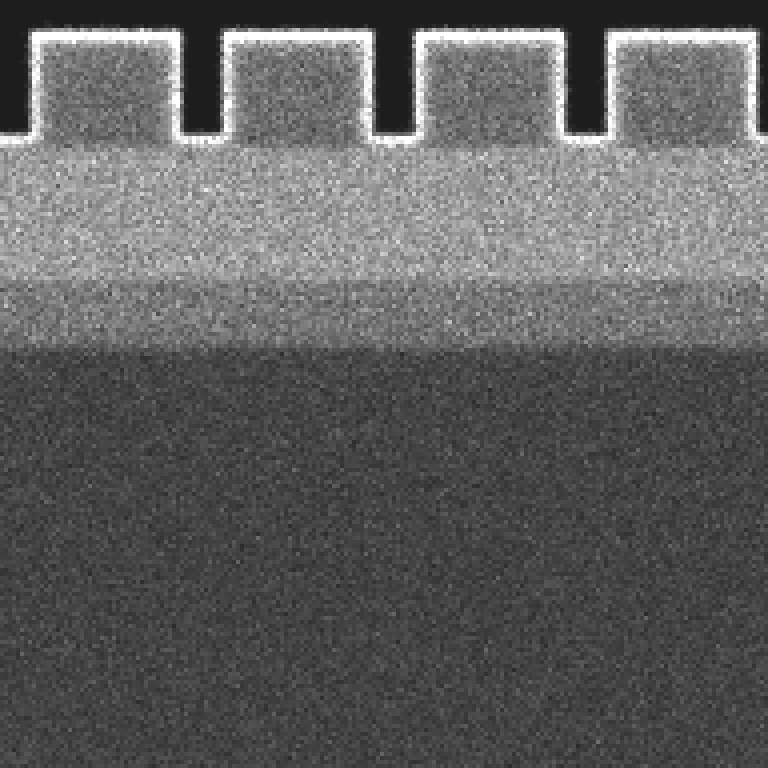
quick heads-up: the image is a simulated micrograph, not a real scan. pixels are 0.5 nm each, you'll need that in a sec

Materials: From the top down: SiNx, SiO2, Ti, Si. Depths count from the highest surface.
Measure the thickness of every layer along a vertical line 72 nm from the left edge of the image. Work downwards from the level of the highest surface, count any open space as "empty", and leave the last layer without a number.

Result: SiNx 58, SiO2 66, Ti 34, Si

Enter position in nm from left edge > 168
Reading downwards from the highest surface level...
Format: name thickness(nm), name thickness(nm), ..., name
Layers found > SiNx 58, SiO2 66, Ti 34, Si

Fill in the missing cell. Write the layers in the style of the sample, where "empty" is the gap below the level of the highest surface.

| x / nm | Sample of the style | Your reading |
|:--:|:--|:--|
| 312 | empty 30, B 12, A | SiNx 58, SiO2 66, Ti 34, Si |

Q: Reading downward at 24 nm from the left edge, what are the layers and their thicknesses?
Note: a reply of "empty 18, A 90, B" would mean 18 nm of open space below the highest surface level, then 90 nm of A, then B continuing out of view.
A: SiNx 58, SiO2 66, Ti 34, Si